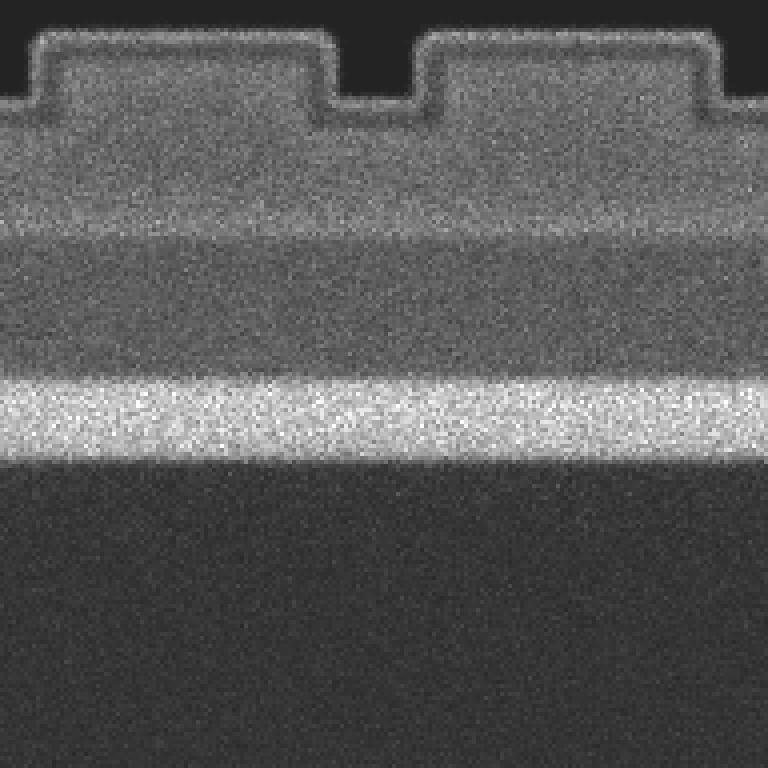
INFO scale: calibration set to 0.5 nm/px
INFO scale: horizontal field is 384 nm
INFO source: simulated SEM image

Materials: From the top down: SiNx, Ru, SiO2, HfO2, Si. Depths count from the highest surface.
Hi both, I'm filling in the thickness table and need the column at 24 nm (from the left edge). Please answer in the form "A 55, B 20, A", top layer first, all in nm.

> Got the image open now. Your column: SiNx 48, Ru 54, SiO2 72, HfO2 40, Si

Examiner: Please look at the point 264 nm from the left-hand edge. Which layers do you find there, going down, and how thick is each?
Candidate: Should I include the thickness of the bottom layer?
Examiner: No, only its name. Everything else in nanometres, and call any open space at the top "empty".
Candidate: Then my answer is SiNx 14, Ru 88, SiO2 72, HfO2 40, Si